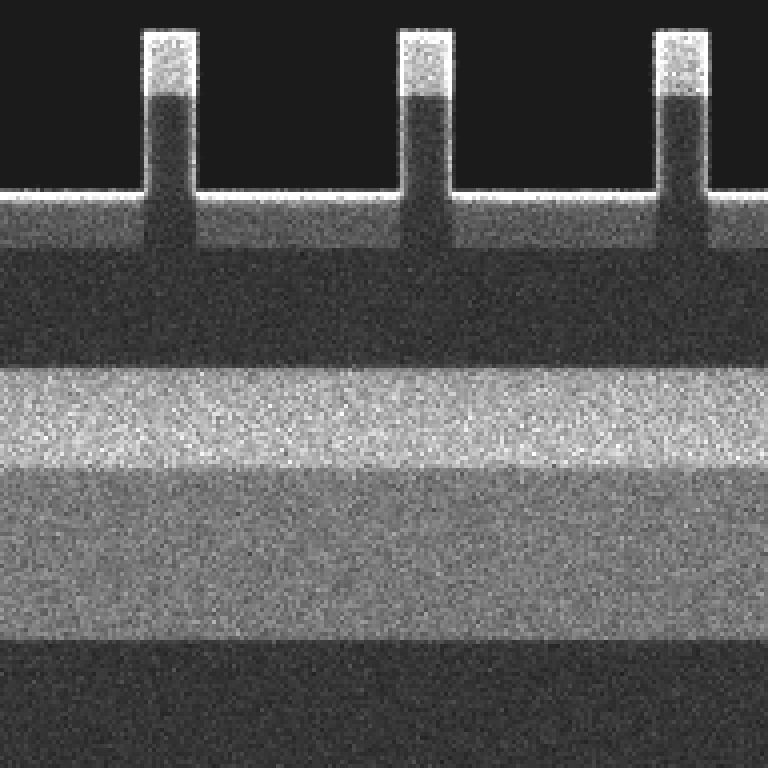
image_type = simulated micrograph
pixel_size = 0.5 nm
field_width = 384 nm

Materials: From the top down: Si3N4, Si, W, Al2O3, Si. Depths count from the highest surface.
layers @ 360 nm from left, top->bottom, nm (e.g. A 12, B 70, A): empty 80, Si3N4 28, Si 60, W 50, Al2O3 86, Si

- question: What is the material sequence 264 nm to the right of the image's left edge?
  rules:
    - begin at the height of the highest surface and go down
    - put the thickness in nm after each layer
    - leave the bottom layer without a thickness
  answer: empty 80, Si3N4 28, Si 60, W 50, Al2O3 86, Si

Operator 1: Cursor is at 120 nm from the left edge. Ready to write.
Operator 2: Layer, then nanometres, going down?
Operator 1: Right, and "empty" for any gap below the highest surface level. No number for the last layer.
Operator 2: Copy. empty 80, Si3N4 28, Si 60, W 50, Al2O3 86, Si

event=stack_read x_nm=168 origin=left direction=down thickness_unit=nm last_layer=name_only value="empty 80, Si3N4 28, Si 60, W 50, Al2O3 86, Si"